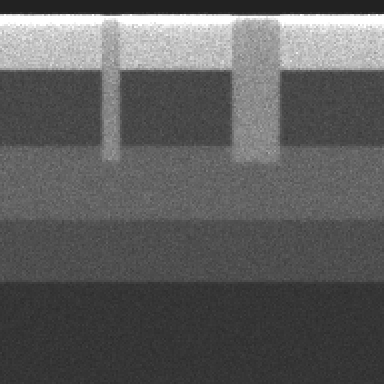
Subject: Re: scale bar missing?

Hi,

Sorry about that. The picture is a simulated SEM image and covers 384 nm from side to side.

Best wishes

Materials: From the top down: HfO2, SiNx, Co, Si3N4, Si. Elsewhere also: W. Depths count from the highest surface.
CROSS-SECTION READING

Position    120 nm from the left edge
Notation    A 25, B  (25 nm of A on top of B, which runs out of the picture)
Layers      HfO2 54, SiNx 76, Co 74, Si3N4 62, Si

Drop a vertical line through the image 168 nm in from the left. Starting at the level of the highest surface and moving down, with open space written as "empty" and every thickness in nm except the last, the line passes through HfO2 54, SiNx 76, Co 74, Si3N4 62, Si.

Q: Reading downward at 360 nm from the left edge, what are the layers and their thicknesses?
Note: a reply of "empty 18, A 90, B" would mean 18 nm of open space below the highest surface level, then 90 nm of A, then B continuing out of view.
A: HfO2 54, SiNx 76, Co 74, Si3N4 62, Si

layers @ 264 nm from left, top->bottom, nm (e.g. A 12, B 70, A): W 146, Co 58, Si3N4 62, Si